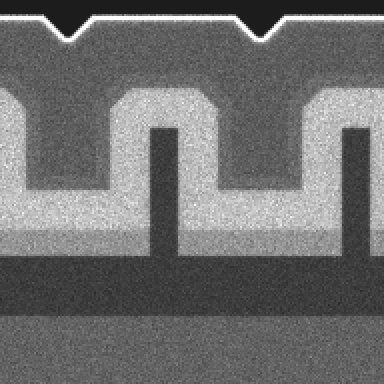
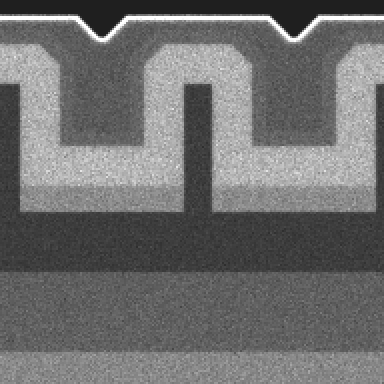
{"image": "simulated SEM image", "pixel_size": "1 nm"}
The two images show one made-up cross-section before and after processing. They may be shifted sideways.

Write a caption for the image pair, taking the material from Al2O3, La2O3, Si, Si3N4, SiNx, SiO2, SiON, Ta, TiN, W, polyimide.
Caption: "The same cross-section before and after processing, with SiNx removed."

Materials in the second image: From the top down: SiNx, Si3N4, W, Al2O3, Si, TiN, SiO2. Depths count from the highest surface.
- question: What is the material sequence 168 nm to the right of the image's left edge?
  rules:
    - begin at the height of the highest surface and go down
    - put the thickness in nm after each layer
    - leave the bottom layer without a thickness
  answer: SiNx 14, Si3N4 14, W 142, Al2O3 26, Si 60, TiN 80, SiO2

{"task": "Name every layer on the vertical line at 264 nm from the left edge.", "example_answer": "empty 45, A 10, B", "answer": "SiNx 40, Si3N4 90, W 40, Al2O3 26, Si 60, TiN 80, SiO2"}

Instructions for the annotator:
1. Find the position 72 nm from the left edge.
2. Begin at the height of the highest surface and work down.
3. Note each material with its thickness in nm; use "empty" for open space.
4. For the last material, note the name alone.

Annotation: SiNx 40, Si3N4 90, W 40, Al2O3 26, Si 60, TiN 80, SiO2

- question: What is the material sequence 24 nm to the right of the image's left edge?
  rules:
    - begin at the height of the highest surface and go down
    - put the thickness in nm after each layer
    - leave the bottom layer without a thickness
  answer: SiNx 14, Si3N4 14, W 142, Al2O3 26, Si 60, TiN 80, SiO2